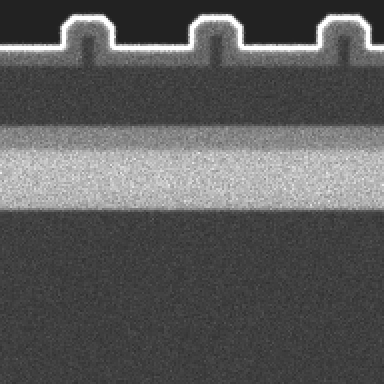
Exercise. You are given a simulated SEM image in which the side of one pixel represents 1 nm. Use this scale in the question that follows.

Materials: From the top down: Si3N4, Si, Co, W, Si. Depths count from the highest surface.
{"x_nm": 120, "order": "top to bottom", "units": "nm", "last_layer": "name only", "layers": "empty 30, Si3N4 20, Si 60, Co 24, W 60, Si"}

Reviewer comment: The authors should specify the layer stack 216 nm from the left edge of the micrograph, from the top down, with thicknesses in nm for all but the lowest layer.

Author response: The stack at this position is Si3N4 20, Si 90, Co 24, W 60, Si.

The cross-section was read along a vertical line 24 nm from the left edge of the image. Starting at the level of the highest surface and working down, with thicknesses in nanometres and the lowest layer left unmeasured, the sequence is empty 30, Si3N4 20, Si 60, Co 24, W 60, Si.